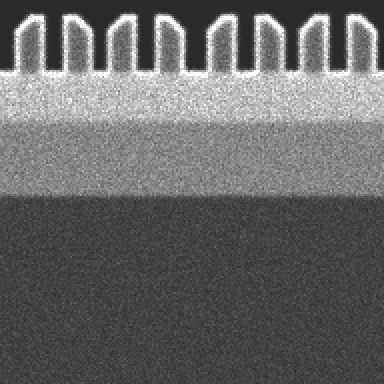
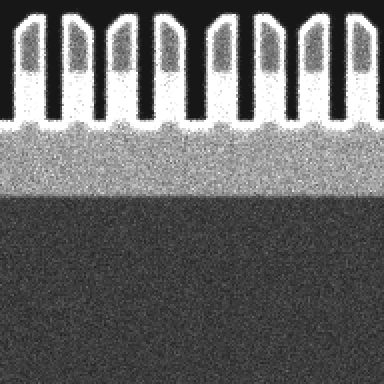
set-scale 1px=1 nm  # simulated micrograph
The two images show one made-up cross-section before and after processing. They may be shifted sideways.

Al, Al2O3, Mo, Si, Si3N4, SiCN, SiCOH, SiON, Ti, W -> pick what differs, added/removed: W removed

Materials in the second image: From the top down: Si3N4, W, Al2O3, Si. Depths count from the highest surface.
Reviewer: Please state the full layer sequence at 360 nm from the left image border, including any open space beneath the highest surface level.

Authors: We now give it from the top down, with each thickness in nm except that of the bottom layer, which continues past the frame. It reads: Si3N4 56, W 50, Al2O3 74, Si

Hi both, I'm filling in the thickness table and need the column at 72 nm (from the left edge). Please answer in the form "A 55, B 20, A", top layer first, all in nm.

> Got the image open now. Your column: Si3N4 56, W 50, Al2O3 74, Si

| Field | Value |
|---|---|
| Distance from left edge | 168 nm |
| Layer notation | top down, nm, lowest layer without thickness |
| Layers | Si3N4 56, W 50, Al2O3 74, Si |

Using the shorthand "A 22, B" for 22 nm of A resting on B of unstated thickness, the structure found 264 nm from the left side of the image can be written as Si3N4 56, W 50, Al2O3 74, Si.